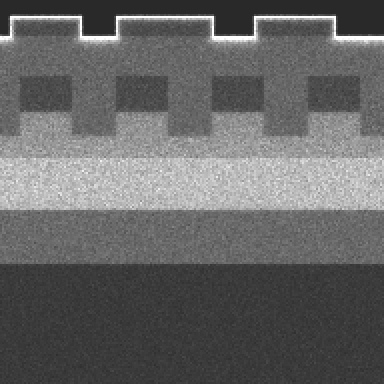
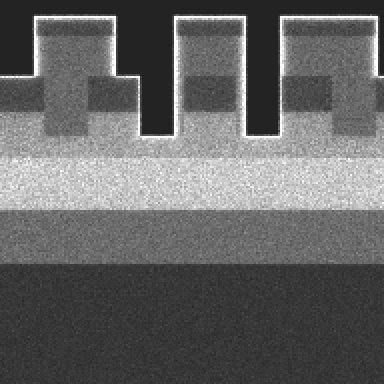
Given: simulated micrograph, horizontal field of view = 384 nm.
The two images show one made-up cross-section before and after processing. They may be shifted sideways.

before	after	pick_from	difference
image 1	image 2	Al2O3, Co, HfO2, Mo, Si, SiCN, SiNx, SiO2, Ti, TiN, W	SiO2 removed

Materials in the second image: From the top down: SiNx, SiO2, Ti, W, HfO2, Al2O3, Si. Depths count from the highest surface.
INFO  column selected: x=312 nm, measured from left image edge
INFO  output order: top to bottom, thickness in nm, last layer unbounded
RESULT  SiNx 20, SiO2 40, Ti 36, W 46, HfO2 52, Al2O3 54, Si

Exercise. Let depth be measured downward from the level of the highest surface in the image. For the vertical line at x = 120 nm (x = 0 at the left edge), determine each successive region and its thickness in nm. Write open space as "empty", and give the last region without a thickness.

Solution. empty 60, Ti 36, W 46, HfO2 52, Al2O3 54, Si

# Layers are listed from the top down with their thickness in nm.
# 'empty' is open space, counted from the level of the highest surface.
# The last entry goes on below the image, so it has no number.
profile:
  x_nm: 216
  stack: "SiNx 20, SiO2 40, Ti 36, W 46, HfO2 52, Al2O3 54, Si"